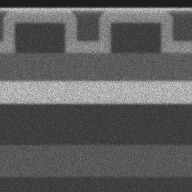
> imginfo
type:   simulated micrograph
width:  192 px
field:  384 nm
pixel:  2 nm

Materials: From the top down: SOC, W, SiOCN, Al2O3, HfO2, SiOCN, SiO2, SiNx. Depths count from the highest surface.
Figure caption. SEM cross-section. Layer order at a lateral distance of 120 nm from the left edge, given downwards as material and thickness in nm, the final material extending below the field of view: SOC 6, W 24, SiOCN 60, Al2O3 56, HfO2 46, SiOCN 82, SiO2 64, SiNx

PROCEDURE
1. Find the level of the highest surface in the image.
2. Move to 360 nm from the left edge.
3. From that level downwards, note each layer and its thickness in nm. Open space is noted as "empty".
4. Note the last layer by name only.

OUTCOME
SOC 66, W 24, Al2O3 56, HfO2 46, SiOCN 82, SiO2 64, SiNx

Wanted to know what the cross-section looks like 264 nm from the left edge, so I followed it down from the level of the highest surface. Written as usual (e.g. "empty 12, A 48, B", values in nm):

SOC 6, W 24, SiOCN 60, Al2O3 56, HfO2 46, SiOCN 82, SiO2 64, SiNx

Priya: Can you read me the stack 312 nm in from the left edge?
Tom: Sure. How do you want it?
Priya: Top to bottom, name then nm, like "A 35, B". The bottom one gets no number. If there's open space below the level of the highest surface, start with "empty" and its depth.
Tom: SOC 6, W 24, SiOCN 60, Al2O3 56, HfO2 46, SiOCN 82, SiO2 64, SiNx